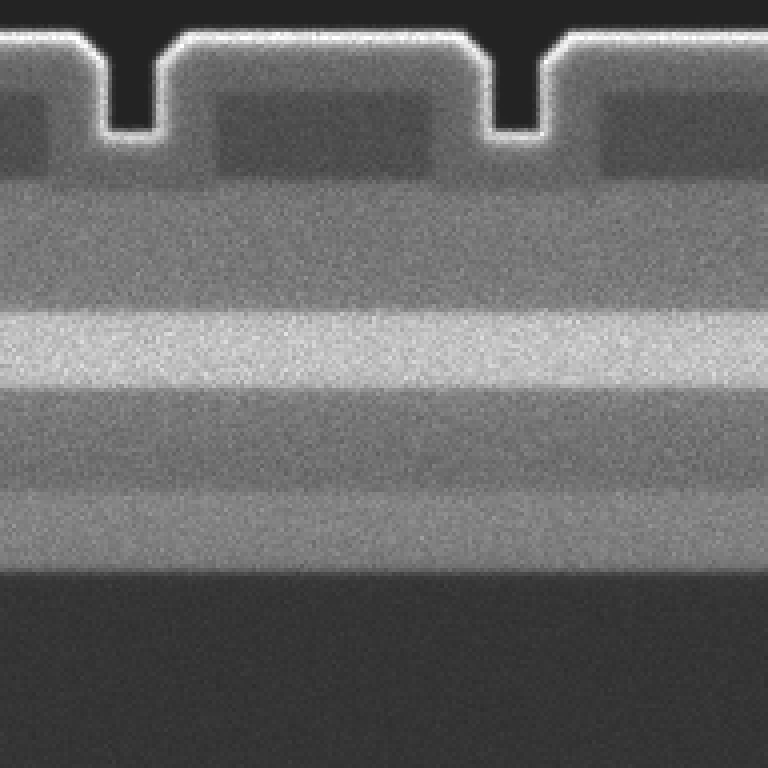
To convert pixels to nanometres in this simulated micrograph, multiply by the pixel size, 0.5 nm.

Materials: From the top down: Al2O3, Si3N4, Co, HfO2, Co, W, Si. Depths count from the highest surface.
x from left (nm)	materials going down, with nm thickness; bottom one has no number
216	Al2O3 80, Co 60, HfO2 38, Co 52, W 40, Si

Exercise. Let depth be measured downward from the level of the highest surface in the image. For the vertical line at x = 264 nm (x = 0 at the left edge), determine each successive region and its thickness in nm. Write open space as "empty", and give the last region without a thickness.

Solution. empty 50, Al2O3 30, Co 60, HfO2 38, Co 52, W 40, Si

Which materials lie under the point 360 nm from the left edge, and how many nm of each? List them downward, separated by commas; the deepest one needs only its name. Al2O3 30, Si3N4 44, Co 66, HfO2 38, Co 52, W 40, Si